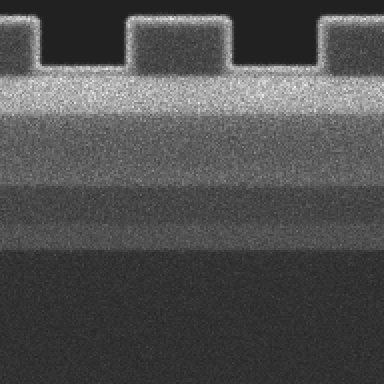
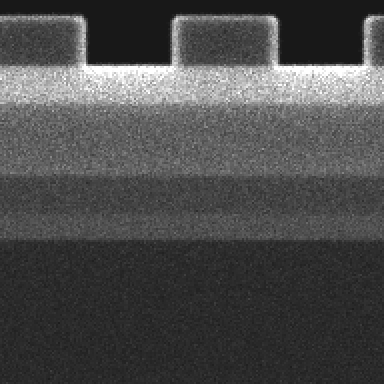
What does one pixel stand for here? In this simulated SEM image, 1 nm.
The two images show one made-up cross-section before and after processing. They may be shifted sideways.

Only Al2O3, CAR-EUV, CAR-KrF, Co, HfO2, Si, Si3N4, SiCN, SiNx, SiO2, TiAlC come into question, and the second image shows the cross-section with Al2O3 removed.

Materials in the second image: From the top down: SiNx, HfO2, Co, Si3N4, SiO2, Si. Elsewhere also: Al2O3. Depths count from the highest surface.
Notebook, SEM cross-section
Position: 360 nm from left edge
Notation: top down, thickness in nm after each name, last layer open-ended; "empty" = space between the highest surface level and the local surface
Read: empty 50, HfO2 38, Co 72, Si3N4 38, SiO2 26, Si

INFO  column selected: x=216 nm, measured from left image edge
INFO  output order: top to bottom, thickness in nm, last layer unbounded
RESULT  SiNx 50, HfO2 38, Co 72, Si3N4 38, SiO2 26, Si